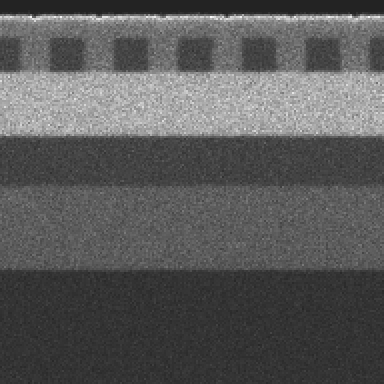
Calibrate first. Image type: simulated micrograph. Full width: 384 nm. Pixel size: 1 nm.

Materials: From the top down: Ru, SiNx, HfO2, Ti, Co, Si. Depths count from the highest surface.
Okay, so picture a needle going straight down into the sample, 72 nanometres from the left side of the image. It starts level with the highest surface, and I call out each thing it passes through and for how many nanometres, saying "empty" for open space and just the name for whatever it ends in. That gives Ru 22, SiNx 34, HfO2 64, Ti 50, Co 84, Si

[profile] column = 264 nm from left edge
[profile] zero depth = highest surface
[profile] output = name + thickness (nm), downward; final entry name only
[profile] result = Ru 22, SiNx 34, HfO2 64, Ti 50, Co 84, Si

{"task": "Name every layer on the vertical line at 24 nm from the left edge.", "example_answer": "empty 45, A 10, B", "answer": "Ru 56, HfO2 64, Ti 50, Co 84, Si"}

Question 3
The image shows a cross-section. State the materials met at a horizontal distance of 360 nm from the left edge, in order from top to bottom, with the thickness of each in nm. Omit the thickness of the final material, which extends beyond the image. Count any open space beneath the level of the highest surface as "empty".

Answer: Ru 56, HfO2 64, Ti 50, Co 84, Si